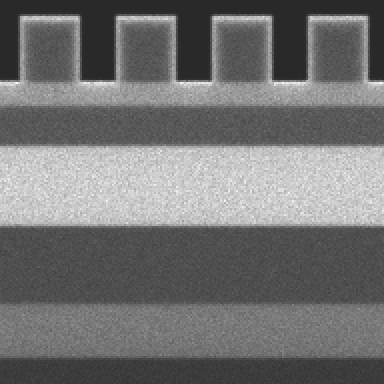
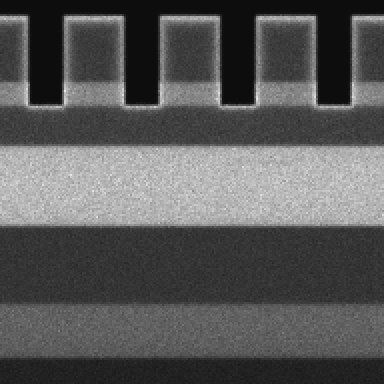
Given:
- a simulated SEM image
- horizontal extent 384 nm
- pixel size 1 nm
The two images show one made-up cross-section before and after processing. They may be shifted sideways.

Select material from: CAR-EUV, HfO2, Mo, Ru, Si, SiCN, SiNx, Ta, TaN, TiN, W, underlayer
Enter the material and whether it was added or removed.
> W / removed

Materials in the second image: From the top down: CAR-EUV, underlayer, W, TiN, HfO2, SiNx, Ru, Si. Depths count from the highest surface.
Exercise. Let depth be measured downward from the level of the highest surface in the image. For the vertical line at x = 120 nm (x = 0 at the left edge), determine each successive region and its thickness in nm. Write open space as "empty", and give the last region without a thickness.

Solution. CAR-EUV 38, underlayer 28, W 24, TiN 40, HfO2 80, SiNx 78, Ru 54, Si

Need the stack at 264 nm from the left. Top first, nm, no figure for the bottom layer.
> CAR-EUV 38, underlayer 28, W 24, TiN 40, HfO2 80, SiNx 78, Ru 54, Si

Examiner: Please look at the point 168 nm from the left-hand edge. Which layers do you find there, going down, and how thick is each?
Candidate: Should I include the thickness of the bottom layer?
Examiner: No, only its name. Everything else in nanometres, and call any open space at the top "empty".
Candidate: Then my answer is CAR-EUV 38, underlayer 28, W 24, TiN 40, HfO2 80, SiNx 78, Ru 54, Si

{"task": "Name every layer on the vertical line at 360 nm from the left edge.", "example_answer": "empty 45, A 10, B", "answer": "CAR-EUV 38, underlayer 28, W 24, TiN 40, HfO2 80, SiNx 78, Ru 54, Si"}